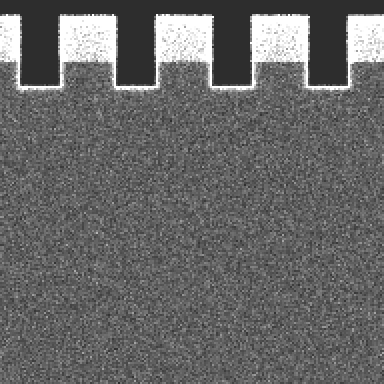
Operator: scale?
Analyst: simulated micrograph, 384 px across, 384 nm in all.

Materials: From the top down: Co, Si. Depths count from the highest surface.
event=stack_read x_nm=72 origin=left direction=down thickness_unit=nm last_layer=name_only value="Co 46, Si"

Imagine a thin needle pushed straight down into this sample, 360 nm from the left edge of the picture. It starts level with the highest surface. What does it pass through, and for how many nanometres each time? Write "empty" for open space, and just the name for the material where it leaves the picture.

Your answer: Co 46, Si